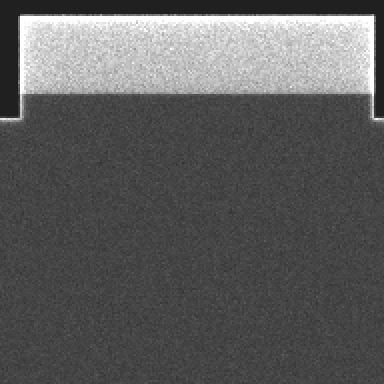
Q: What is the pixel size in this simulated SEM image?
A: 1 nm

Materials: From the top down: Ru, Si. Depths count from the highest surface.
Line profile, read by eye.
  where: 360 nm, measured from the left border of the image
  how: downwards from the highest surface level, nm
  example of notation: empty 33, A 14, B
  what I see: Ru 78, Si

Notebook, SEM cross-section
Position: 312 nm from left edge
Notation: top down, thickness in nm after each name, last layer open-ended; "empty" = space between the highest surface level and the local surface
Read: Ru 78, Si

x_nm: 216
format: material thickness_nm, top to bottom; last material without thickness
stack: Ru 78, Si